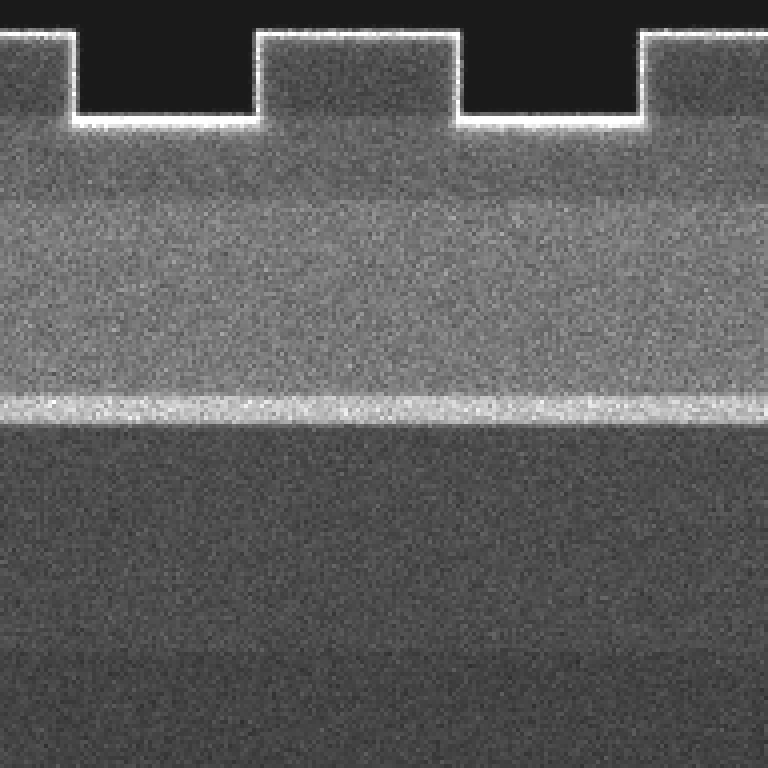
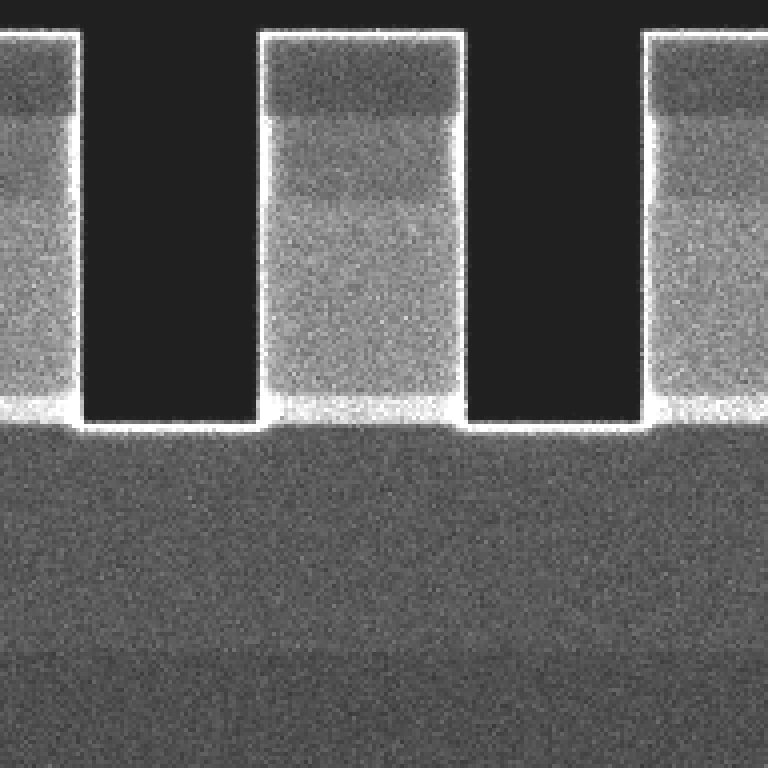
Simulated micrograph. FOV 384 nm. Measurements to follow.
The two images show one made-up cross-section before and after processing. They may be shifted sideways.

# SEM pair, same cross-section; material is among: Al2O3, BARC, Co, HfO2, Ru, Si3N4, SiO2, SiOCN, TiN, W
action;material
removed;HfO2 and Ru and SiO2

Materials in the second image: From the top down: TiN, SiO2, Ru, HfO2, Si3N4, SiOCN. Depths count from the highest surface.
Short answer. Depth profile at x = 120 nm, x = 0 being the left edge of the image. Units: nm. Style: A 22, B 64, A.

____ empty 196, Si3N4 114, SiOCN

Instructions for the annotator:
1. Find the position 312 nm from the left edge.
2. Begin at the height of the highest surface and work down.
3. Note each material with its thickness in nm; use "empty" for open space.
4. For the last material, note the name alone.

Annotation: empty 196, Si3N4 114, SiOCN